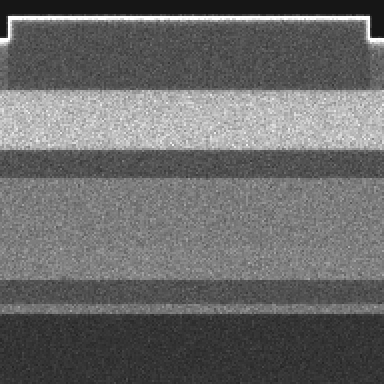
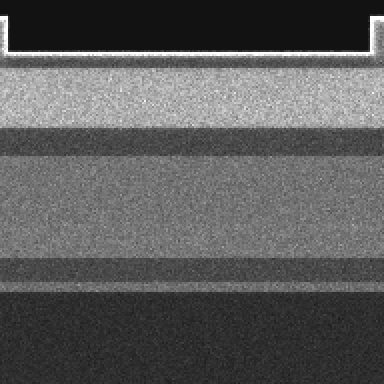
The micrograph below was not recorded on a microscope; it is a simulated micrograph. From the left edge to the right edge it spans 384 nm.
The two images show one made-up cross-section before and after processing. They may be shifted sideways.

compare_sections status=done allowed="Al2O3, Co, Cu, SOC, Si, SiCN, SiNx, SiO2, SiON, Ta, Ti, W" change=removed material="SiNx"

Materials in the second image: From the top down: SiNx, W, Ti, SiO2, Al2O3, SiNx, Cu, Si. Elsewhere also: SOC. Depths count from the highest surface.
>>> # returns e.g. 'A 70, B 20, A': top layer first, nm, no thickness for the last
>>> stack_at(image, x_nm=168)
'empty 36, SiNx 16, W 60, Ti 28, SiO2 68, Al2O3 34, SiNx 24, Cu 10, Si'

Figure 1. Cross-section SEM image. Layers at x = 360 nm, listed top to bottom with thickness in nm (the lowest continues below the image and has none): empty 36, SiNx 16, W 60, Ti 28, SiO2 68, Al2O3 34, SiNx 24, Cu 10, Si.